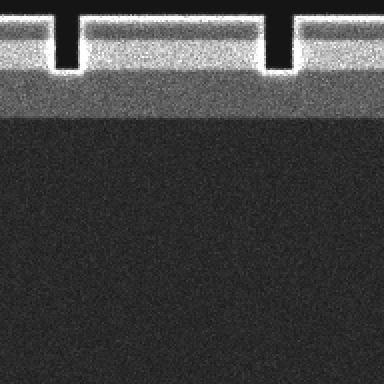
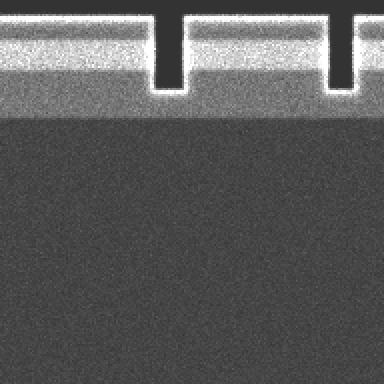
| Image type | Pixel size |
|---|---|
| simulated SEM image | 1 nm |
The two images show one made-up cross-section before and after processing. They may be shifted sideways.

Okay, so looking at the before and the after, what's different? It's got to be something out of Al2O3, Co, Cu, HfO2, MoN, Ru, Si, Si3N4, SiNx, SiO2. Al2O3, removed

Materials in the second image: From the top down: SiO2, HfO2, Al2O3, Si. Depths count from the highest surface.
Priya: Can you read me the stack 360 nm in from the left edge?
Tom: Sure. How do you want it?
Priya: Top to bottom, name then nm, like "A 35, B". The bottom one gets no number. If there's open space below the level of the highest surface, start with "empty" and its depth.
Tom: SiO2 24, HfO2 30, Al2O3 48, Si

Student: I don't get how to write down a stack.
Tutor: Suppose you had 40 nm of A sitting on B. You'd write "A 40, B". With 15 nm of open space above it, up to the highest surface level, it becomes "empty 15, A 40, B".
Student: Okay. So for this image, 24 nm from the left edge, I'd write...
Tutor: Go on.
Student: SiO2 24, HfO2 30, Al2O3 48, Si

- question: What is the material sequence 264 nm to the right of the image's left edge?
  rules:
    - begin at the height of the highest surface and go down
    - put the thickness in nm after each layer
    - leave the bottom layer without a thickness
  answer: SiO2 24, HfO2 30, Al2O3 48, Si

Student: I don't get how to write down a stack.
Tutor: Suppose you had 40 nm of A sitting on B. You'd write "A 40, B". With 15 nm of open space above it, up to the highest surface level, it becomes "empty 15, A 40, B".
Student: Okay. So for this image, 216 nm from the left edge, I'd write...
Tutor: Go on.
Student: SiO2 24, HfO2 30, Al2O3 48, Si